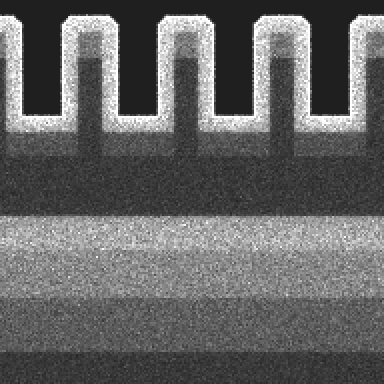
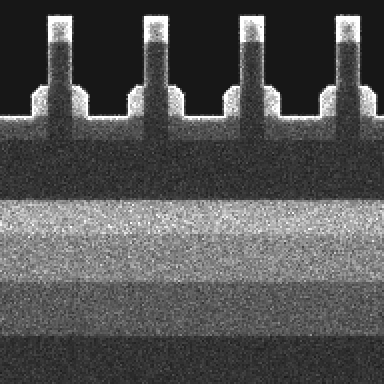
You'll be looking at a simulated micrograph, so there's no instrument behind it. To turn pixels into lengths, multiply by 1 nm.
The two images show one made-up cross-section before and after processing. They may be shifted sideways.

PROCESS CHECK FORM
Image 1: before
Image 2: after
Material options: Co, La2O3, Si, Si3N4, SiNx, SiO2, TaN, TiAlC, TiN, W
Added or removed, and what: removed, W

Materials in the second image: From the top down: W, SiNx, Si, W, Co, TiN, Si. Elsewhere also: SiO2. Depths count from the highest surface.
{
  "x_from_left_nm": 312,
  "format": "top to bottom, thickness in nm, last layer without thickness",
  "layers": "empty 100, SiNx 24, Si 60, W 34, Co 48, TiN 54, Si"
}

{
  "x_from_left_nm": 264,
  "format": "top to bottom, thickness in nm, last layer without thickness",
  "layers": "empty 70, W 30, SiNx 24, Si 60, W 34, Co 48, TiN 54, Si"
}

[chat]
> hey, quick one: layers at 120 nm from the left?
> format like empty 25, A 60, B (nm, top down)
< empty 100, SiNx 24, Si 60, W 34, Co 48, TiN 54, Si